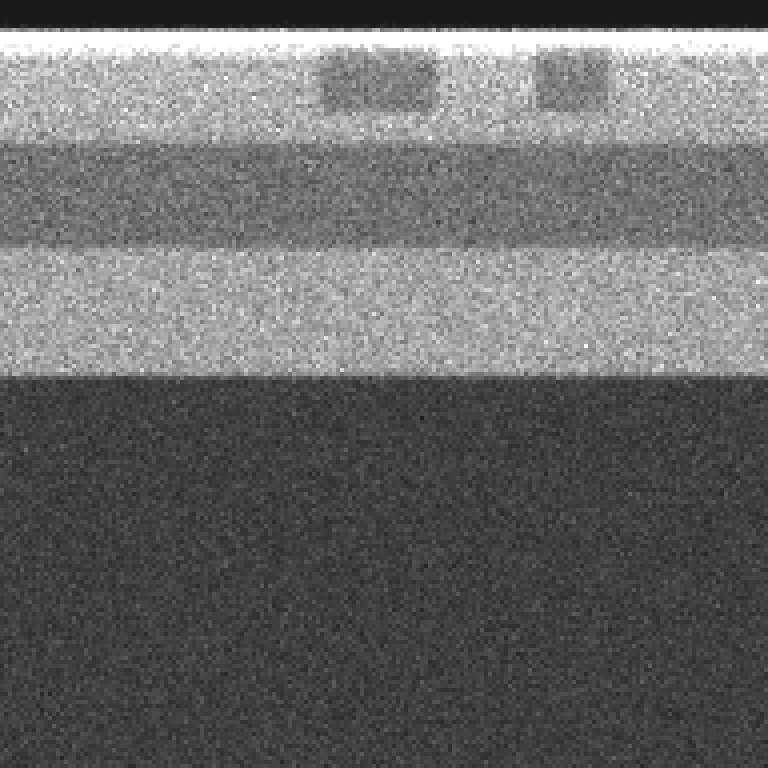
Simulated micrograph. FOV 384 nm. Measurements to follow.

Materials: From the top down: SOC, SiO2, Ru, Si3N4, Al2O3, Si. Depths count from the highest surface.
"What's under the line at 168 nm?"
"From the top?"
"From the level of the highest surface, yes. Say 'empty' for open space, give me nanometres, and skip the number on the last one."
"SOC 40, Ru 16, Si3N4 52, Al2O3 64, Si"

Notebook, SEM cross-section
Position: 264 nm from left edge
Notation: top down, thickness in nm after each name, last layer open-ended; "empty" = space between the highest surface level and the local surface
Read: SOC 8, SiO2 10, Ru 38, Si3N4 52, Al2O3 64, Si